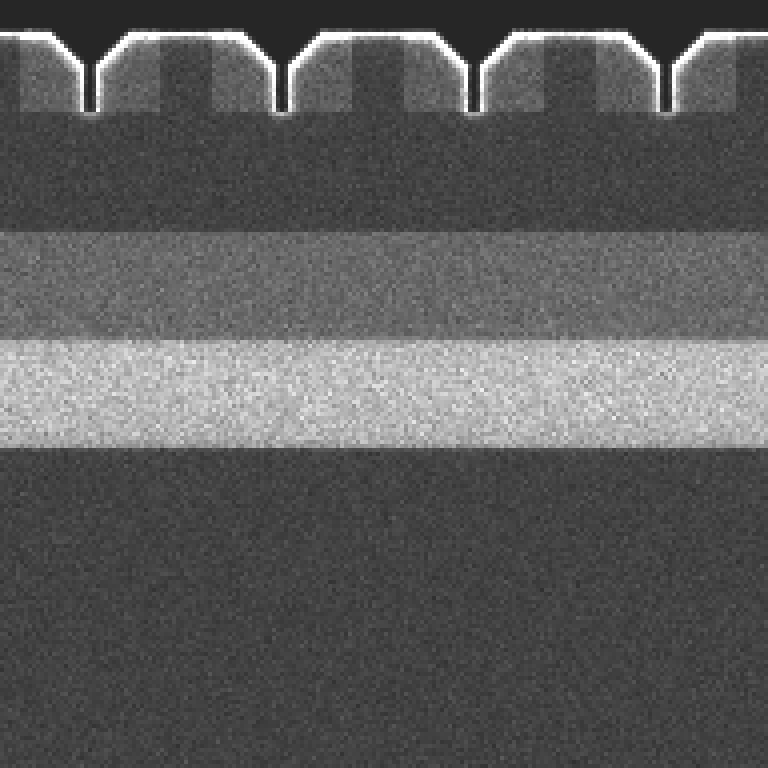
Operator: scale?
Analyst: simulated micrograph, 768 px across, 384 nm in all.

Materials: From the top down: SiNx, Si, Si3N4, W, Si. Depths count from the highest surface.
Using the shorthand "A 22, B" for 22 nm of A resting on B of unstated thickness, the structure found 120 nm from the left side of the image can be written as SiNx 40, Si 60, Si3N4 54, W 54, Si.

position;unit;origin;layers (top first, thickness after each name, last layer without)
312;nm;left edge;SiNx 40, Si 60, Si3N4 54, W 54, Si